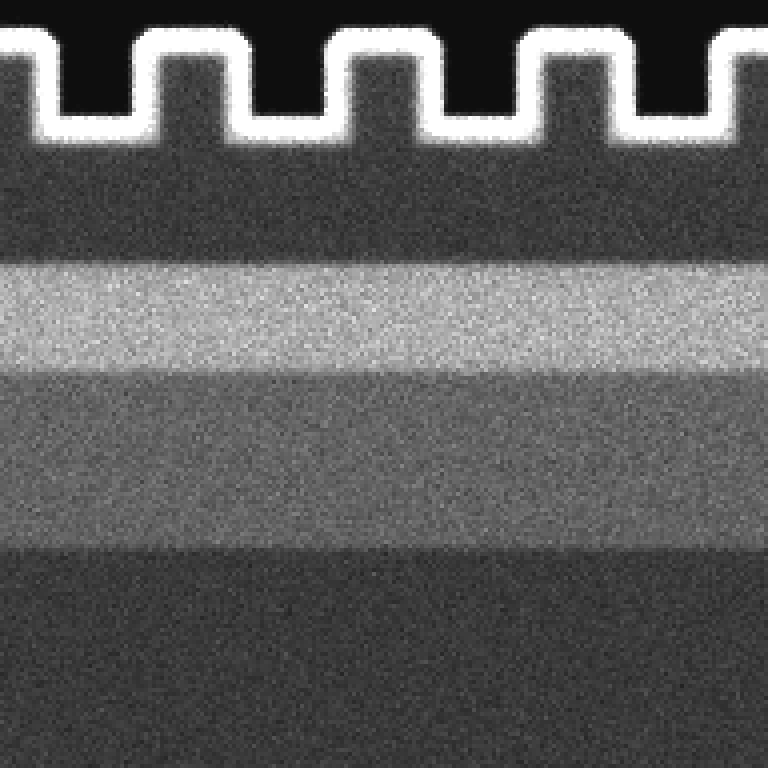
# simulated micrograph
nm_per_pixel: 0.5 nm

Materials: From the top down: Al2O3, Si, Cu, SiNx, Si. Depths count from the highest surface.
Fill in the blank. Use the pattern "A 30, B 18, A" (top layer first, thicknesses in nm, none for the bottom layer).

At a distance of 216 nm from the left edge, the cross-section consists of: empty 4, Al2O3 52, Si 60, Cu 54, SiNx 88, Si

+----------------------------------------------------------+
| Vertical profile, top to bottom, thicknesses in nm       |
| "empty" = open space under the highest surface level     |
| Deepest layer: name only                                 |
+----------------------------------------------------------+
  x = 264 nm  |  empty 2, Al2O3 54, Si 60, Cu 54, SiNx 88, Si